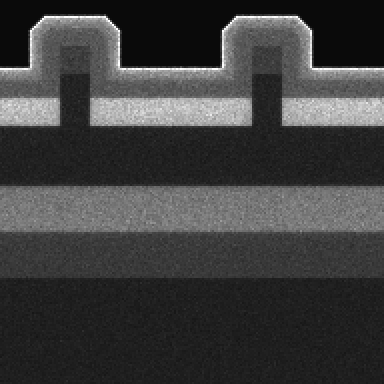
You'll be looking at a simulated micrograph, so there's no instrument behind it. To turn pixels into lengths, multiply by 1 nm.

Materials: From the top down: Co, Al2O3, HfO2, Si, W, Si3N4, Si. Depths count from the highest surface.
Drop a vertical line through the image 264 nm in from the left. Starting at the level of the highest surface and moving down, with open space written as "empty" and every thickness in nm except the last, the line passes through Co 12, Al2O3 18, Si3N4 28, Si 112, W 46, Si3N4 46, Si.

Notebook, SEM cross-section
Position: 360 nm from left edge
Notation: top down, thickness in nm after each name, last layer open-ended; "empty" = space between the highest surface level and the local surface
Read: empty 52, Co 12, Al2O3 18, HfO2 28, Si 60, W 46, Si3N4 46, Si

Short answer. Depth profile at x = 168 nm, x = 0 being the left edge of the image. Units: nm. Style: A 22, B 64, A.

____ empty 52, Co 12, Al2O3 18, HfO2 28, Si 60, W 46, Si3N4 46, Si